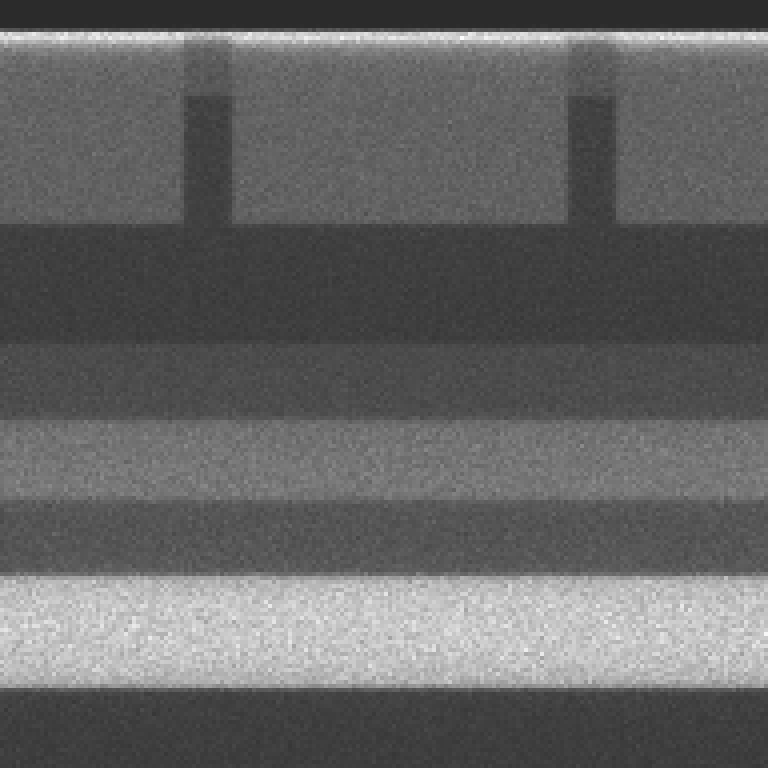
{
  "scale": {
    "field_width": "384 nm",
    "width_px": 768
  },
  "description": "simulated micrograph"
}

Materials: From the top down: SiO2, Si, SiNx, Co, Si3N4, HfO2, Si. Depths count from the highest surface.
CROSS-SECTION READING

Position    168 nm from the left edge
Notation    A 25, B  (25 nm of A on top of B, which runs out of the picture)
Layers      SiO2 96, Si 60, SiNx 38, Co 40, Si3N4 38, HfO2 56, Si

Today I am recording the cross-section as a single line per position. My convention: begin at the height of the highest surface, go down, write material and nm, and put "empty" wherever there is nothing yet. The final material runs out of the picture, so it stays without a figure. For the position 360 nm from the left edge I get SiO2 96, Si 60, SiNx 38, Co 40, Si3N4 38, HfO2 56, Si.